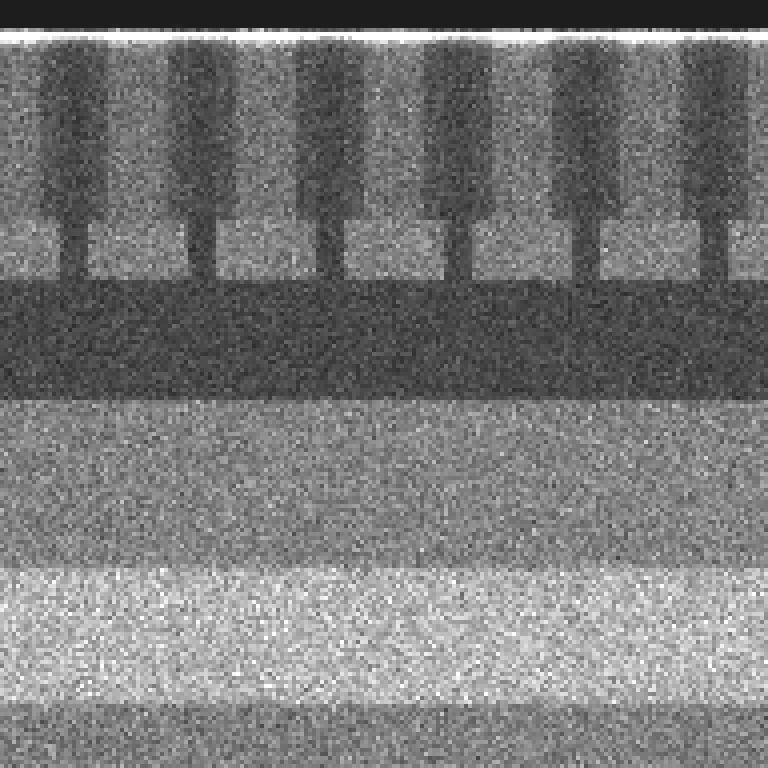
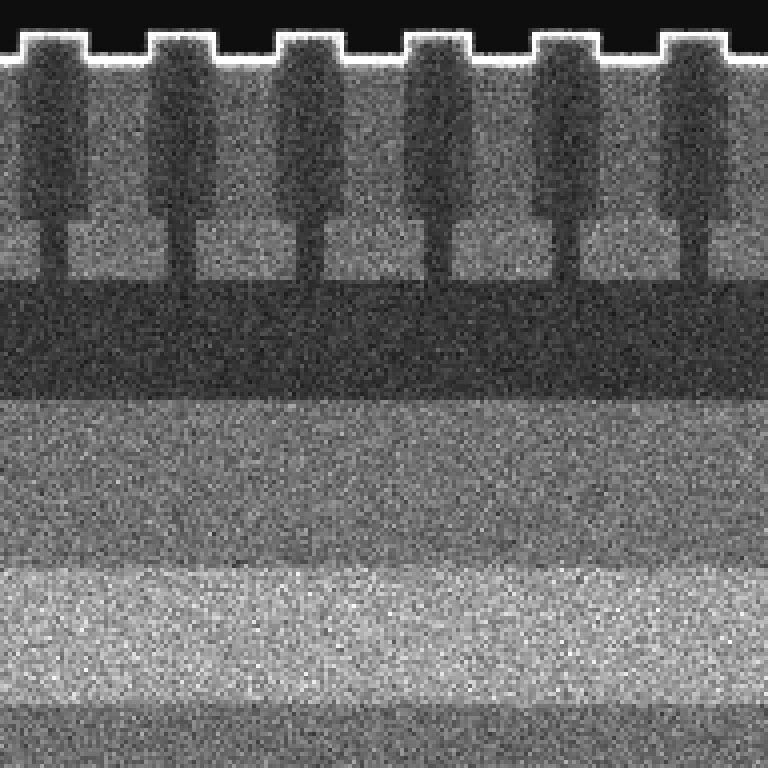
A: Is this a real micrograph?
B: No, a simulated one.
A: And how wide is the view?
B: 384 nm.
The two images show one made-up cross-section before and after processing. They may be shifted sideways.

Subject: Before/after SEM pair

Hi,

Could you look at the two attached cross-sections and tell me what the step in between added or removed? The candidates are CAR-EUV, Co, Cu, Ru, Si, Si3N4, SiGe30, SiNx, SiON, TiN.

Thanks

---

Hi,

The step removed SiNx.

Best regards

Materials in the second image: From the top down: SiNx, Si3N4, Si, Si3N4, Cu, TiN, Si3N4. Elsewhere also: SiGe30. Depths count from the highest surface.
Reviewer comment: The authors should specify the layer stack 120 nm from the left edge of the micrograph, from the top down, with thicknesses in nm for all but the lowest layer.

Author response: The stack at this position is empty 12, SiNx 82, Si3N4 30, Si 60, Si3N4 84, Cu 68, TiN 30, Si3N4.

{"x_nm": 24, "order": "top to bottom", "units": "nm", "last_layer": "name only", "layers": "Si 184, Si3N4 84, Cu 68, TiN 30, Si3N4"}